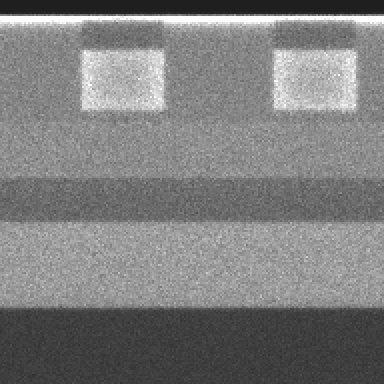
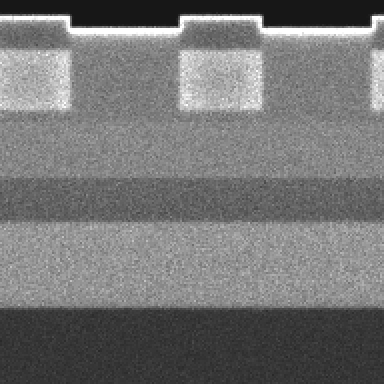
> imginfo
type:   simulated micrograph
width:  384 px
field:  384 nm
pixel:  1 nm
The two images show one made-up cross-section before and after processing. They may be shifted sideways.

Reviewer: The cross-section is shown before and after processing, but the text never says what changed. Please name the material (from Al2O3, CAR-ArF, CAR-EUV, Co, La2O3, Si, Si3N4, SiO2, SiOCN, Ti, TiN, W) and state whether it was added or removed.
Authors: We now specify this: SiO2, removed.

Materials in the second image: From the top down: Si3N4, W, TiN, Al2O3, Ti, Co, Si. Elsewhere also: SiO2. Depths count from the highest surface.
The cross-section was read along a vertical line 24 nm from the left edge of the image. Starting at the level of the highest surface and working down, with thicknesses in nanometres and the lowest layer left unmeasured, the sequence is Si3N4 34, W 60, TiN 12, Al2O3 56, Ti 44, Co 86, Si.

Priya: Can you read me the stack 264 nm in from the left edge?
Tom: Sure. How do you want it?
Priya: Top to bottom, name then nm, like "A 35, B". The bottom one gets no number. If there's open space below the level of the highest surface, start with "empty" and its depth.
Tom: empty 12, SiO2 94, Al2O3 56, Ti 44, Co 86, Si